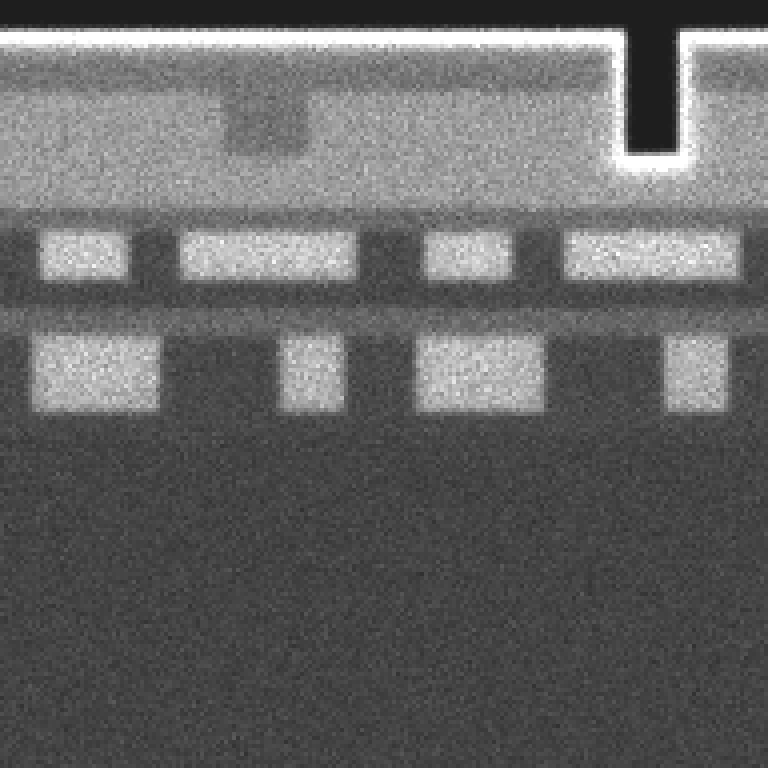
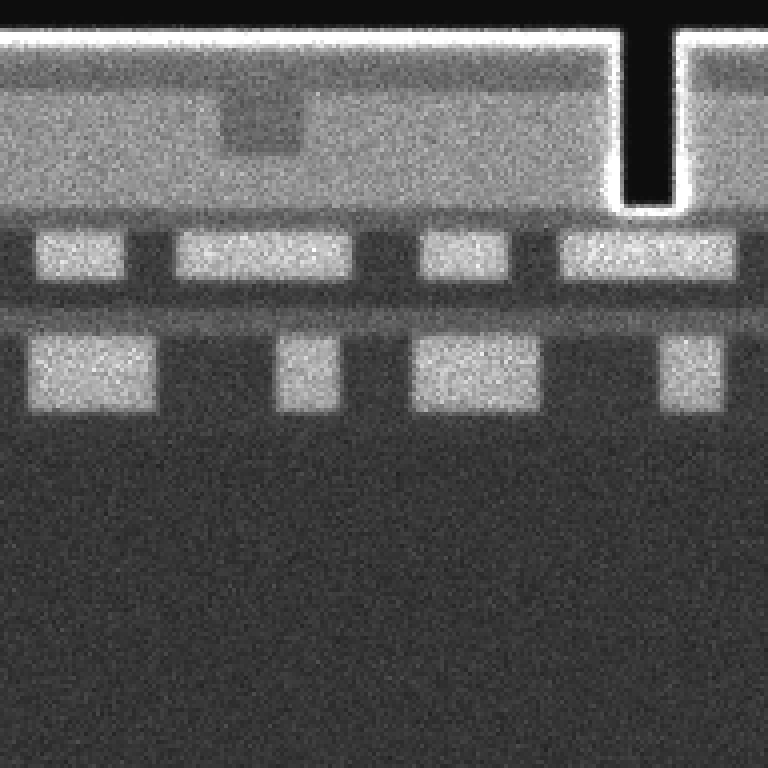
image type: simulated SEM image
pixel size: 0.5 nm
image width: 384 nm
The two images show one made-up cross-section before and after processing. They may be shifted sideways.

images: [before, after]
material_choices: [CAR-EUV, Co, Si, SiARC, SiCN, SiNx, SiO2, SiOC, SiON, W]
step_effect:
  removed: SiO2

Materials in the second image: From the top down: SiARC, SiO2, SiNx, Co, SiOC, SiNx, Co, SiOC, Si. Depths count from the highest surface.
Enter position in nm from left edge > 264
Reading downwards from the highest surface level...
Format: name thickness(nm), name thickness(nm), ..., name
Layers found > SiARC 30, SiO2 58, SiNx 12, SiOC 38, SiNx 14, Co 38, SiOC 12, Si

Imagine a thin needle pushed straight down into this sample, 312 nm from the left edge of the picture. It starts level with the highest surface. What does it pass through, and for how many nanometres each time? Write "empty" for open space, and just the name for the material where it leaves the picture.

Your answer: empty 88, SiNx 12, Co 24, SiOC 14, SiNx 14, SiOC 50, Si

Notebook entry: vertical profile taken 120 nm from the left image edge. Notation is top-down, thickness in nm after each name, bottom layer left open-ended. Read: SiARC 62, SiO2 26, SiNx 12, Co 24, SiOC 14, SiNx 14, SiOC 50, Si